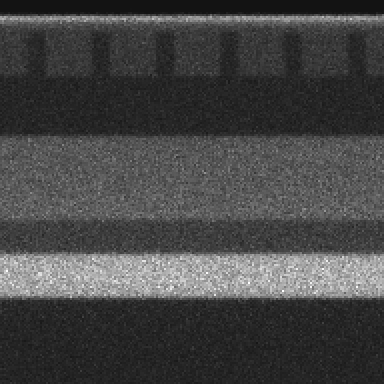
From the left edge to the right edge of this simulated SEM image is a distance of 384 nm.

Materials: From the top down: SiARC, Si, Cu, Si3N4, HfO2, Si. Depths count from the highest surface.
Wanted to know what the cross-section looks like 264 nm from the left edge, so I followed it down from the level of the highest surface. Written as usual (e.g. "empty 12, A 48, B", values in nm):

SiARC 60, Si 60, Cu 84, Si3N4 34, HfO2 44, Si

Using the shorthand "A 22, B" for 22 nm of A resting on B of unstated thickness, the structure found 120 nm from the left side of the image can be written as SiARC 60, Si 60, Cu 84, Si3N4 34, HfO2 44, Si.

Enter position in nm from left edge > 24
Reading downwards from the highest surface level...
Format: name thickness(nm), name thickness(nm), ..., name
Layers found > SiARC 60, Si 60, Cu 84, Si3N4 34, HfO2 44, Si